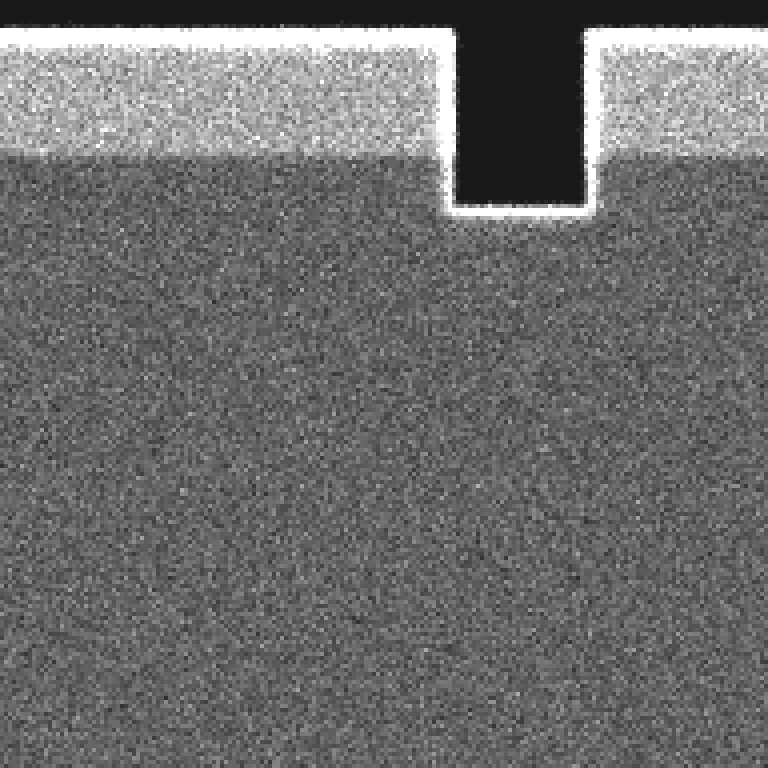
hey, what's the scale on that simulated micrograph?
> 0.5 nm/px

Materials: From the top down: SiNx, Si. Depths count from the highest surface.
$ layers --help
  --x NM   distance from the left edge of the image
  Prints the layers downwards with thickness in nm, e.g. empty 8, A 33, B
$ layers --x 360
SiNx 62, Si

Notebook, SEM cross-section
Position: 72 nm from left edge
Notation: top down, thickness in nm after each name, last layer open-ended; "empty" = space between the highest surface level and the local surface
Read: SiNx 62, Si